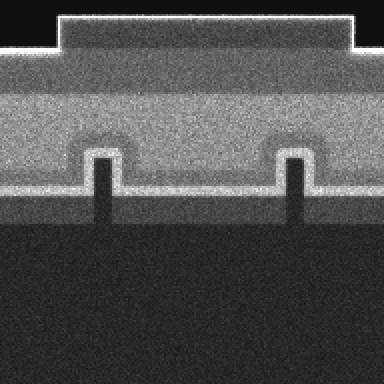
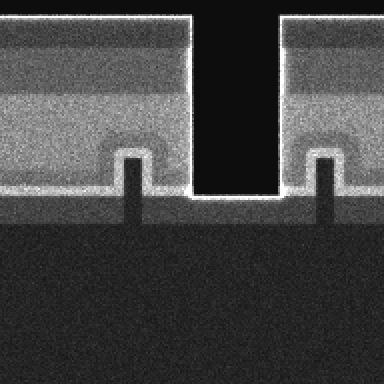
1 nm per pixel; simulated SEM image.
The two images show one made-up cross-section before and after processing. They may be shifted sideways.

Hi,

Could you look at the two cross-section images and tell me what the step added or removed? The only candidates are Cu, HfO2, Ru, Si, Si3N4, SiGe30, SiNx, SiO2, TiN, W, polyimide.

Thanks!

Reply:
removed HfO2 and Ru and SiO2 and W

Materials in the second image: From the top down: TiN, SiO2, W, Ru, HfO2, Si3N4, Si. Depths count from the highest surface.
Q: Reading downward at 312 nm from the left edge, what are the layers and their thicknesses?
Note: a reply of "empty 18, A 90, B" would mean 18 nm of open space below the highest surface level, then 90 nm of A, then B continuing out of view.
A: TiN 32, SiO2 46, W 38, Ru 16, HfO2 48, Si3N4 28, Si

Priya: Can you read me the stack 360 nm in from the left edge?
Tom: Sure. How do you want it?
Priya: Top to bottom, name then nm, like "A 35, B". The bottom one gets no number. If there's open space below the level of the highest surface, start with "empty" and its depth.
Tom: TiN 32, SiO2 46, W 76, Ru 16, HfO2 10, Si3N4 28, Si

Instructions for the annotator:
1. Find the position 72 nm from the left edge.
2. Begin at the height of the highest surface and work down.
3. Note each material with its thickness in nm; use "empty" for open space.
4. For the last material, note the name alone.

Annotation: TiN 32, SiO2 46, W 76, Ru 16, HfO2 10, Si3N4 28, Si